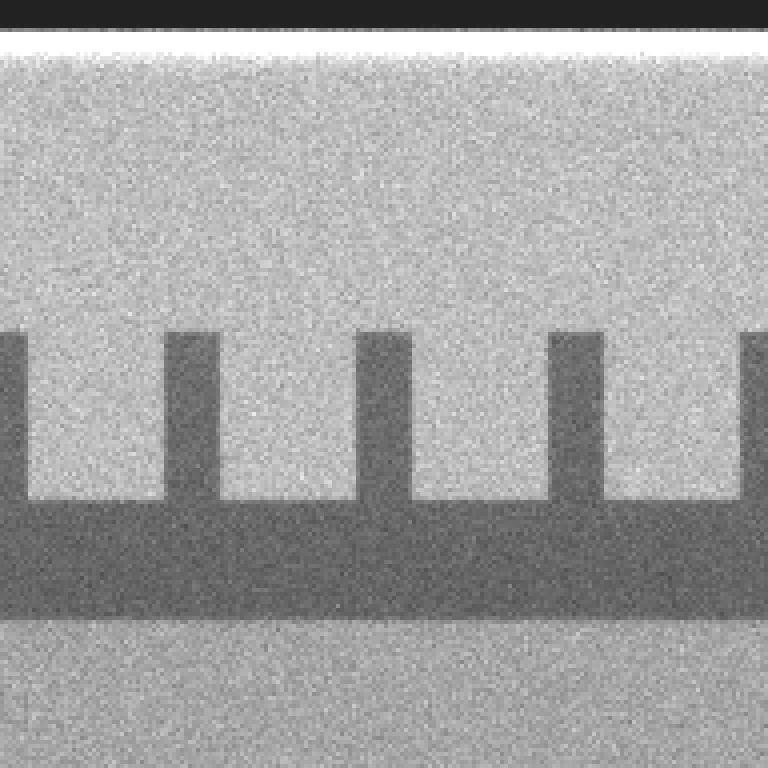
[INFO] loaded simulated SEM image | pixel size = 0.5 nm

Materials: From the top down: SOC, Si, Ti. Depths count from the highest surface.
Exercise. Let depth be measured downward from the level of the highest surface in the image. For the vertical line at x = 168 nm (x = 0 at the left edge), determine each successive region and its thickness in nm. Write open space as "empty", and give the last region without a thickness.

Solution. SOC 234, Si 60, Ti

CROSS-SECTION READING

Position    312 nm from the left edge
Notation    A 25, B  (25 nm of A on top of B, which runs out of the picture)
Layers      SOC 234, Si 60, Ti